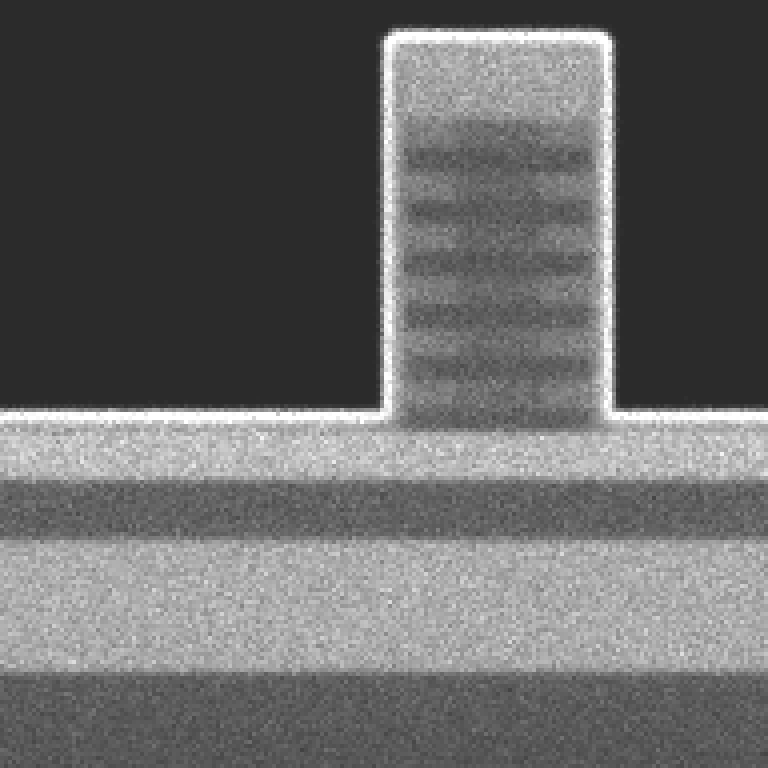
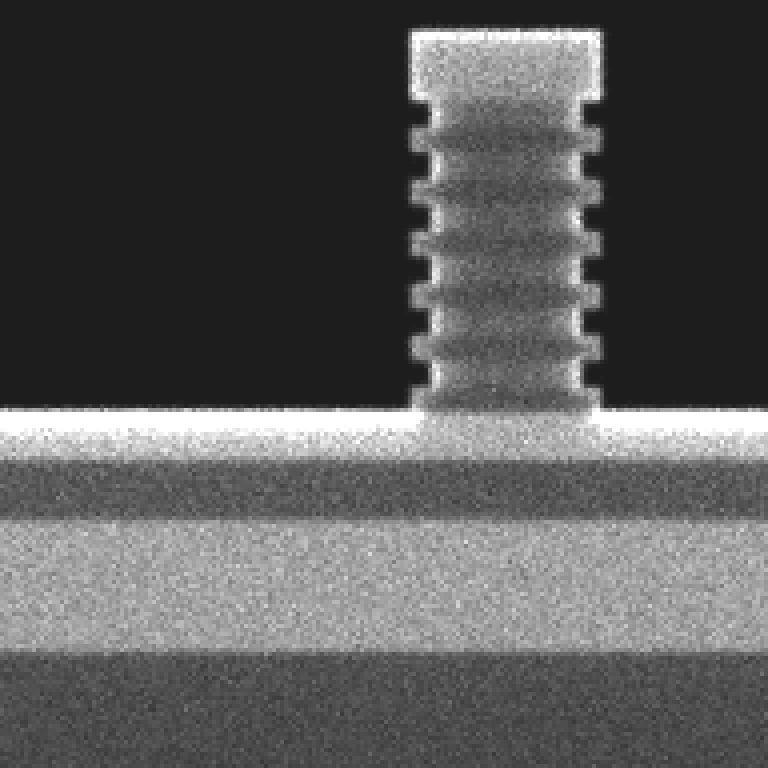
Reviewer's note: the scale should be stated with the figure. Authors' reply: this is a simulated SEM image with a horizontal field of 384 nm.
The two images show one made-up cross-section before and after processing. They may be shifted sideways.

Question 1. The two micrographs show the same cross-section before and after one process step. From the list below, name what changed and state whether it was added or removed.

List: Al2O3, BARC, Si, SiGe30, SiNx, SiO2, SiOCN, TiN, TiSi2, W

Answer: SiNx, removed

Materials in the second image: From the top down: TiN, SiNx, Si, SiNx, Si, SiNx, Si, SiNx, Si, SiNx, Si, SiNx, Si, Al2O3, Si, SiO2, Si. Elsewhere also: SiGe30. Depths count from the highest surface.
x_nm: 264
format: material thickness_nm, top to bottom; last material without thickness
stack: TiN 34, SiGe30 14, Si 12, SiGe30 14, Si 12, SiGe30 14, Si 12, SiGe30 14, Si 12, SiGe30 14, Si 12, SiGe30 14, Si 12, Al2O3 24, Si 30, SiO2 66, Si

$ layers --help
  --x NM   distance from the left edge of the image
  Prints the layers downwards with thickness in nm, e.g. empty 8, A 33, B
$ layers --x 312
empty 190, Al2O3 24, Si 30, SiO2 66, Si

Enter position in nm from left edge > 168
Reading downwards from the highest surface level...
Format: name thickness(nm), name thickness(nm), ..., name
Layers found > empty 190, Al2O3 24, Si 30, SiO2 66, Si